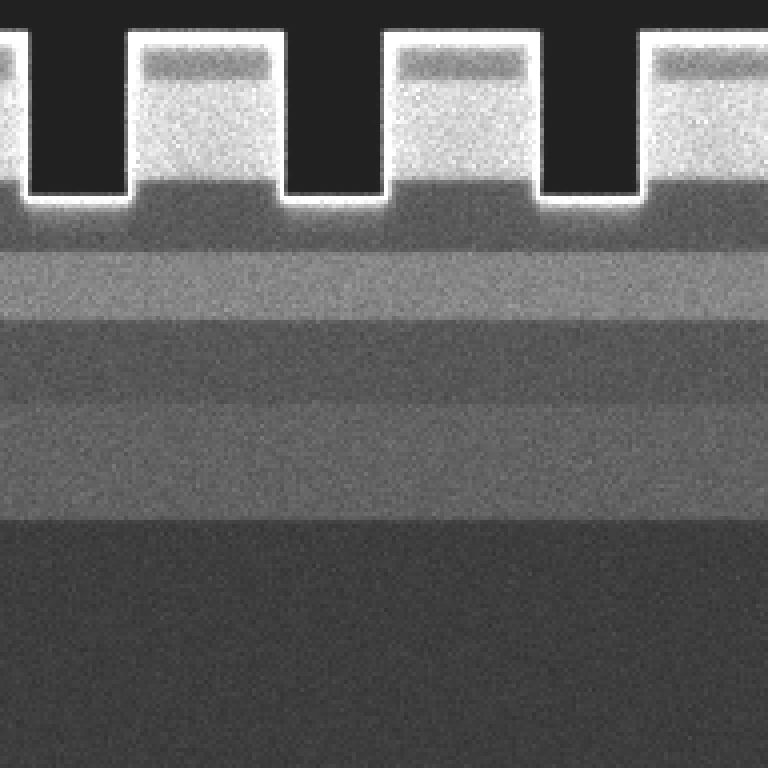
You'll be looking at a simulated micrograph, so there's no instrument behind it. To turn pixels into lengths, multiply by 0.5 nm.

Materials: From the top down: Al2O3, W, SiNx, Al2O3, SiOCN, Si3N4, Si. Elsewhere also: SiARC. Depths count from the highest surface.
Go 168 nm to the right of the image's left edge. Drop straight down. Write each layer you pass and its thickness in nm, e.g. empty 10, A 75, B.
empty 82, SiARC 18, SiNx 10, Al2O3 34, SiOCN 42, Si3N4 58, Si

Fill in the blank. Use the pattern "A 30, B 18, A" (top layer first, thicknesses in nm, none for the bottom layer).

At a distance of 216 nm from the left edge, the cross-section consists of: Al2O3 24, W 50, SiNx 36, Al2O3 34, SiOCN 42, Si3N4 58, Si